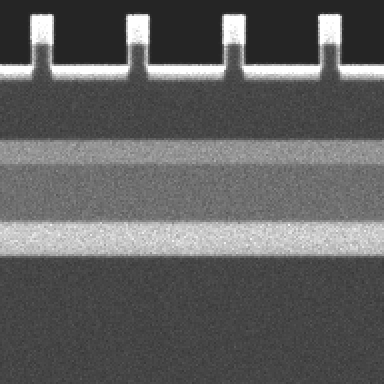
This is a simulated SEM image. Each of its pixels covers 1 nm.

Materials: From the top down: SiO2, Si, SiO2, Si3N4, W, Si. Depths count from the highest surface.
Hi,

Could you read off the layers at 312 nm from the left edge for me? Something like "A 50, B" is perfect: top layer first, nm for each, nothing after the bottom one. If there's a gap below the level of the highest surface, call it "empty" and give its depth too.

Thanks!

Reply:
empty 50, SiO2 14, Si 60, SiO2 24, Si3N4 58, W 34, Si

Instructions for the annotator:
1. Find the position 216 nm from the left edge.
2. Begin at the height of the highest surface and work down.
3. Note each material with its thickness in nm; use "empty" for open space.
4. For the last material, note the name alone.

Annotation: empty 50, SiO2 14, Si 60, SiO2 24, Si3N4 58, W 34, Si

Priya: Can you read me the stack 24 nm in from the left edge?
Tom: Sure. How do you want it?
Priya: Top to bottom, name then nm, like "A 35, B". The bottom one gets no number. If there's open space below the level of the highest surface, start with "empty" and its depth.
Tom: empty 50, SiO2 14, Si 60, SiO2 24, Si3N4 58, W 34, Si